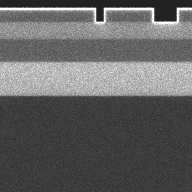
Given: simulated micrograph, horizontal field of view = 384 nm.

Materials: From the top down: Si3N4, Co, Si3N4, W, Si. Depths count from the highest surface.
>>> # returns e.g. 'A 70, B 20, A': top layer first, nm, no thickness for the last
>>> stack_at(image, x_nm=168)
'Si3N4 28, Co 34, Si3N4 46, W 68, Si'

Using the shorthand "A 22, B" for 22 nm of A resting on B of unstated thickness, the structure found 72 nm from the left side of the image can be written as Si3N4 28, Co 34, Si3N4 46, W 68, Si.